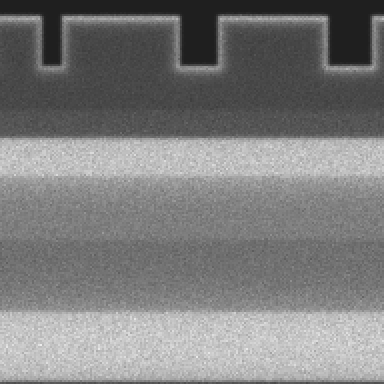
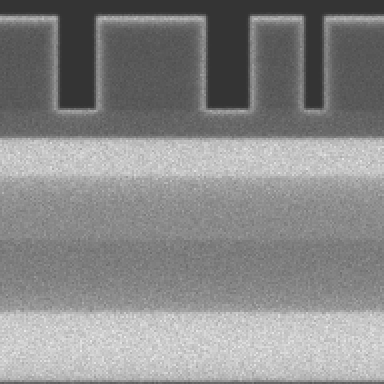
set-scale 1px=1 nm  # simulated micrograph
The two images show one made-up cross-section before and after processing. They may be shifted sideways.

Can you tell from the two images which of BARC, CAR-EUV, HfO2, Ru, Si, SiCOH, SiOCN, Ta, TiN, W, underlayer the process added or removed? Yes, it removed underlayer.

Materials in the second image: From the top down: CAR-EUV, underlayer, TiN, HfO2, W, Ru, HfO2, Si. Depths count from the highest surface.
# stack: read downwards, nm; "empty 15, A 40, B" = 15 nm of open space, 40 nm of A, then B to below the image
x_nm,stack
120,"CAR-EUV 50, underlayer 44, TiN 28, HfO2 38, W 64, Ru 72, HfO2 70, Si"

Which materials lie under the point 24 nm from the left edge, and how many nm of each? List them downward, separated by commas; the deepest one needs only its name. CAR-EUV 50, underlayer 44, TiN 28, HfO2 38, W 64, Ru 72, HfO2 70, Si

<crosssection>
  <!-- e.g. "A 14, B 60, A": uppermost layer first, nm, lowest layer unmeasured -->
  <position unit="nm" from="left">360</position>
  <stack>CAR-EUV 50, underlayer 44, TiN 28, HfO2 38, W 64, Ru 72, HfO2 70, Si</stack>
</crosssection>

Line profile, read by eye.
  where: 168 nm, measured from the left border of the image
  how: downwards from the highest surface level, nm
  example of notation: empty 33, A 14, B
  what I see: CAR-EUV 50, underlayer 44, TiN 28, HfO2 38, W 64, Ru 72, HfO2 70, Si